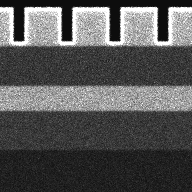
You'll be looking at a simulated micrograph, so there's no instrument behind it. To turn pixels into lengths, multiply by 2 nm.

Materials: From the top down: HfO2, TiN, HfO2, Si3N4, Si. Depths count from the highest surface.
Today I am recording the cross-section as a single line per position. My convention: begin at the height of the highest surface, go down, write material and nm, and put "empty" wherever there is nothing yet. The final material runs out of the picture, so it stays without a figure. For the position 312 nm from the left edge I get HfO2 76, TiN 80, HfO2 50, Si3N4 78, Si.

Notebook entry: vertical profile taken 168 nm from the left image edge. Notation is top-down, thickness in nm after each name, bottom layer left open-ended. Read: HfO2 76, TiN 80, HfO2 50, Si3N4 78, Si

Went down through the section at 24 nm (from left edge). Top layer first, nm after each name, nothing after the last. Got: HfO2 76, TiN 80, HfO2 50, Si3N4 78, Si